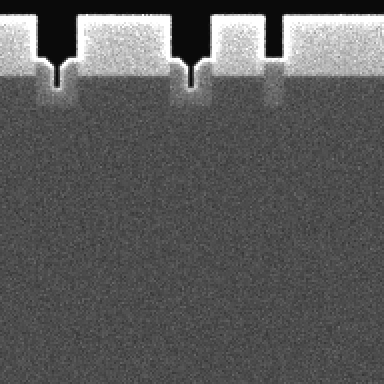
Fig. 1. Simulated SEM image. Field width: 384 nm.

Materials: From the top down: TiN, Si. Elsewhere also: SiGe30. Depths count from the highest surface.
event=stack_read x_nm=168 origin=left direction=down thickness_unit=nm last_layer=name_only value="TiN 60, Si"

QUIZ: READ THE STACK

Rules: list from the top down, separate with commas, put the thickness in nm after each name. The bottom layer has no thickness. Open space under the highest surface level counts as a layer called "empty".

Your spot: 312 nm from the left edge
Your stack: TiN 60, Si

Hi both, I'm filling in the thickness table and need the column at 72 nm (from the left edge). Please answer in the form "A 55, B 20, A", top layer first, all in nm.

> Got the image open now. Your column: empty 42, SiGe30 48, Si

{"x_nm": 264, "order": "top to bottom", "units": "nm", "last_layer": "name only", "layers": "empty 42, SiGe30 48, Si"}